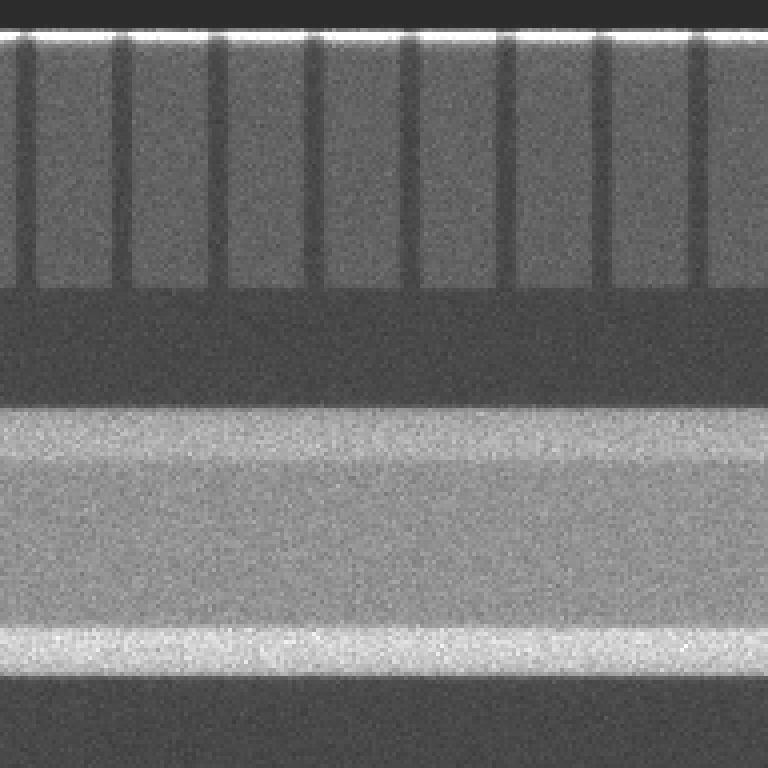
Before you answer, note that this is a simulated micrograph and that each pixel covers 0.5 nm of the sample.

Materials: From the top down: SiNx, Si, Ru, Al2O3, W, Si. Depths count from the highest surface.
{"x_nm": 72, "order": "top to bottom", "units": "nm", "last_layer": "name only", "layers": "SiNx 128, Si 60, Ru 26, Al2O3 84, W 24, Si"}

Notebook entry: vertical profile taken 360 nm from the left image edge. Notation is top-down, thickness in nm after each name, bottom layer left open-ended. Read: SiNx 128, Si 60, Ru 26, Al2O3 84, W 24, Si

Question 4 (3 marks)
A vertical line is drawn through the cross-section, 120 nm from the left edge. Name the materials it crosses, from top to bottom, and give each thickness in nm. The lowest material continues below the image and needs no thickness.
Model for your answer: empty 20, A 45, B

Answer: SiNx 128, Si 60, Ru 26, Al2O3 84, W 24, Si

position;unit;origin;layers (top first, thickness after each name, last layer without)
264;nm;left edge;SiNx 128, Si 60, Ru 26, Al2O3 84, W 24, Si